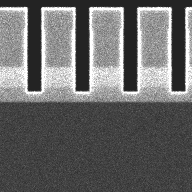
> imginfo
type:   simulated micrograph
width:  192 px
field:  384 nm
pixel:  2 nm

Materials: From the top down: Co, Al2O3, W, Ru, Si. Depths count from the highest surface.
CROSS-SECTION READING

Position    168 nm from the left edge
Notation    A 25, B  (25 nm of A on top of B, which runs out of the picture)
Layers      empty 168, Ru 20, Si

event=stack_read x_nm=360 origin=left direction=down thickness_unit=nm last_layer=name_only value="empty 168, Ru 20, Si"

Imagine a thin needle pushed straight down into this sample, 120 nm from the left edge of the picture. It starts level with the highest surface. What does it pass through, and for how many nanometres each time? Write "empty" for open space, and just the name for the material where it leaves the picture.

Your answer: Co 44, Al2O3 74, W 40, Ru 30, Si